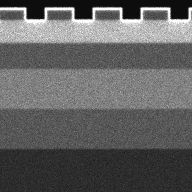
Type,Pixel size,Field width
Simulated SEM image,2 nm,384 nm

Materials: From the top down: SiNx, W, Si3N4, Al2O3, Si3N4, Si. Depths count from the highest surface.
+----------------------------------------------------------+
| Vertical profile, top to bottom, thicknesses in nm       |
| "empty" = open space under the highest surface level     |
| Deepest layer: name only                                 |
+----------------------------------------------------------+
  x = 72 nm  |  empty 24, W 46, Si3N4 52, Al2O3 80, Si3N4 80, Si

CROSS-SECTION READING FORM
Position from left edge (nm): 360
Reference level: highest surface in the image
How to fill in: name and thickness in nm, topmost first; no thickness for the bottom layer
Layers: empty 24, W 46, Si3N4 52, Al2O3 80, Si3N4 80, Si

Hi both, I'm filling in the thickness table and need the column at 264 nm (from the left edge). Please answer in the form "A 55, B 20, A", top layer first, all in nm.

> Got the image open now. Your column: empty 24, W 46, Si3N4 52, Al2O3 80, Si3N4 80, Si